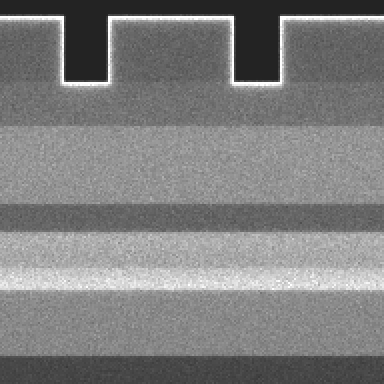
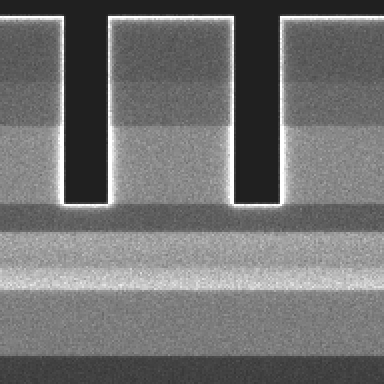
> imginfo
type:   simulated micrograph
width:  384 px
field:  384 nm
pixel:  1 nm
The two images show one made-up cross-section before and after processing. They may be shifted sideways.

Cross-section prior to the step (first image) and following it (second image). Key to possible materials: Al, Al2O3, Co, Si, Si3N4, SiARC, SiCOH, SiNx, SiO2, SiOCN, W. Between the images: Al2O3 and Si3N4 was removed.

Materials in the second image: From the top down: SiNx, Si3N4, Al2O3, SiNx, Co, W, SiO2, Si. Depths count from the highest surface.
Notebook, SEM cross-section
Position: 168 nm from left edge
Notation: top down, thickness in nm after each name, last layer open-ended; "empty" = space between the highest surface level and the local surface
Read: SiNx 66, Si3N4 44, Al2O3 78, SiNx 28, Co 36, W 22, SiO2 66, Si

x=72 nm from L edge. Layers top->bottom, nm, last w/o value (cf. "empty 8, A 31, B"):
empty 188, SiNx 28, Co 36, W 22, SiO2 66, Si